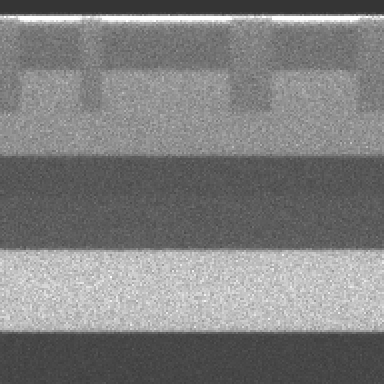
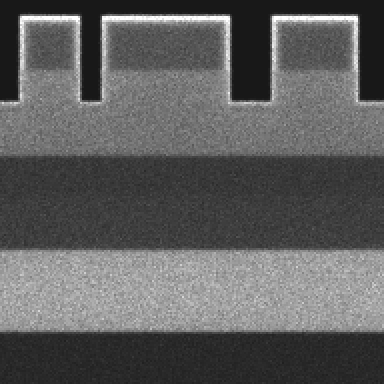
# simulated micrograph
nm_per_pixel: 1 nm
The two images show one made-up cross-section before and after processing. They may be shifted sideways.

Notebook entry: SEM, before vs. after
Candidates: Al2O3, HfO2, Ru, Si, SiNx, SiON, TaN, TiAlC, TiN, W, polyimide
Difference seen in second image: Ru removed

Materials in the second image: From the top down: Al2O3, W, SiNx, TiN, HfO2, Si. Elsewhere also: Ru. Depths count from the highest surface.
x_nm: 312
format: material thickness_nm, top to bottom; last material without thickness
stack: Al2O3 54, W 86, SiNx 40, TiN 54, HfO2 82, Si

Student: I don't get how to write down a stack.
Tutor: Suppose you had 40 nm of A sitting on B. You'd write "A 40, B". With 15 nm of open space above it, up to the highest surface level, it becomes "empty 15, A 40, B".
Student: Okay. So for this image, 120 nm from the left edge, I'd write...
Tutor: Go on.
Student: Al2O3 54, W 86, SiNx 40, TiN 54, HfO2 82, Si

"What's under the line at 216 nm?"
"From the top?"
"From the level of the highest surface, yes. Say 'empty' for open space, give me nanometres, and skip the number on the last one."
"Al2O3 54, W 86, SiNx 40, TiN 54, HfO2 82, Si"